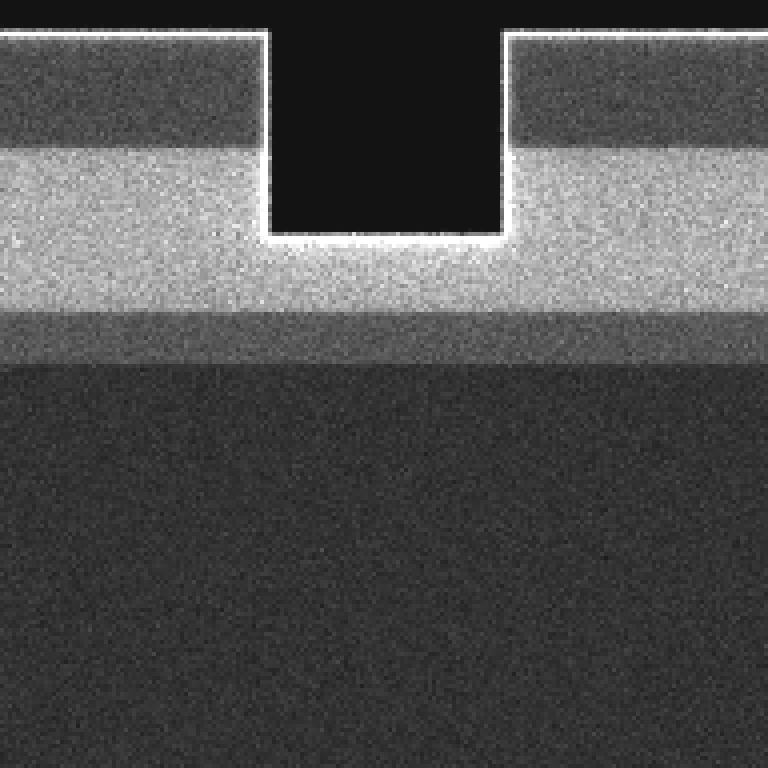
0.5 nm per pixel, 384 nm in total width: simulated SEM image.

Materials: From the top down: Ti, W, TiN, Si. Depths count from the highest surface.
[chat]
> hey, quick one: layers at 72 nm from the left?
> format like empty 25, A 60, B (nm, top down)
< Ti 58, W 82, TiN 26, Si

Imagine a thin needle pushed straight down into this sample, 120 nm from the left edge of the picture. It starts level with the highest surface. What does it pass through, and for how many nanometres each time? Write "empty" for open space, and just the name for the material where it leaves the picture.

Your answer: Ti 58, W 82, TiN 26, Si